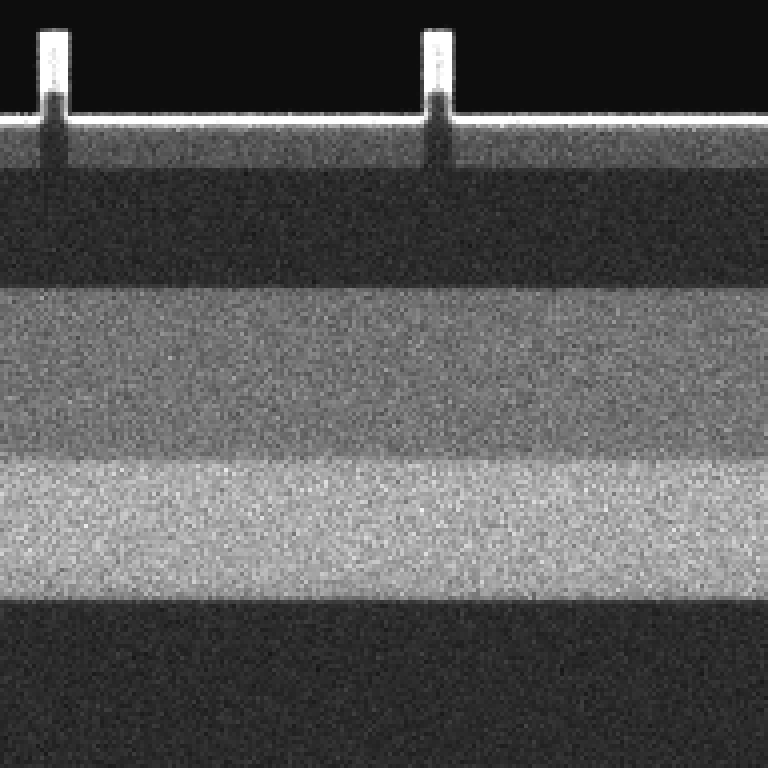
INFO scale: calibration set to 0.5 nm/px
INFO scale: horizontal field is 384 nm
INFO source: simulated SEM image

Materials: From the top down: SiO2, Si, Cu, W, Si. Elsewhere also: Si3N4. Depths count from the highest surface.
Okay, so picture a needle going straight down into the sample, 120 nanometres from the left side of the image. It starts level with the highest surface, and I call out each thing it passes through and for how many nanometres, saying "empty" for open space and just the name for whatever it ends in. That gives empty 42, Si3N4 26, Si 60, Cu 86, W 70, Si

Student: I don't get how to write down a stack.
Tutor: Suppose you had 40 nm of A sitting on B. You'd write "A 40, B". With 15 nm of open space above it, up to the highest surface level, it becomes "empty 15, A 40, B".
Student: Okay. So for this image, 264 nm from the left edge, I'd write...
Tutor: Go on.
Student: empty 42, Si3N4 26, Si 60, Cu 86, W 70, Si